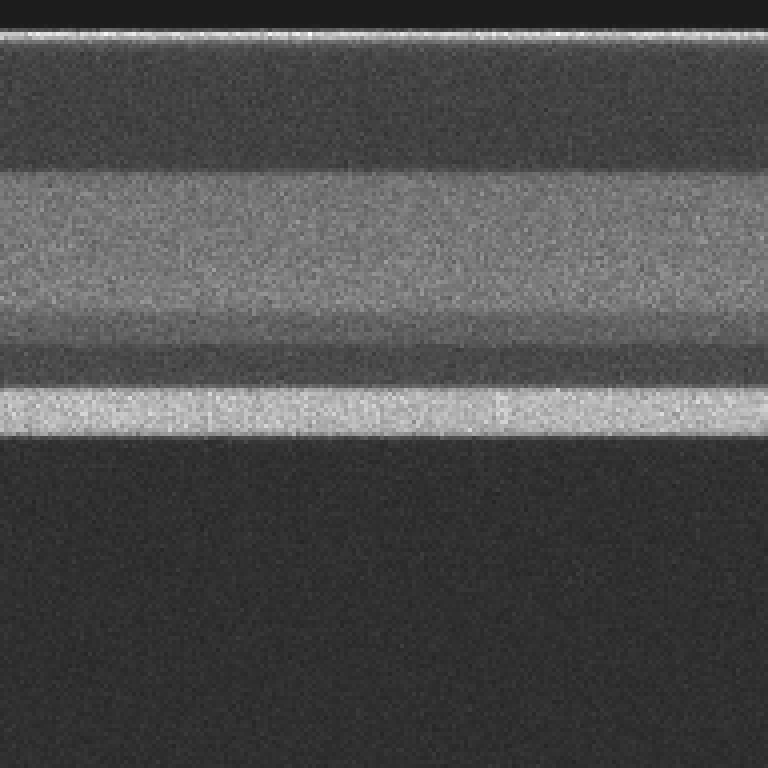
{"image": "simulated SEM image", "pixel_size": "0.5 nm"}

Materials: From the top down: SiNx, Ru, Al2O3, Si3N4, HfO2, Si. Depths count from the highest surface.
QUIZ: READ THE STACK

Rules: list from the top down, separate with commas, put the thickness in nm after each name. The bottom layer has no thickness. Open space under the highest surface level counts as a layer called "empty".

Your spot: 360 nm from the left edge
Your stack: SiNx 70, Ru 70, Al2O3 16, Si3N4 22, HfO2 24, Si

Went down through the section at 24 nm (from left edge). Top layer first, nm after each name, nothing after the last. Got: SiNx 70, Ru 70, Al2O3 16, Si3N4 22, HfO2 24, Si